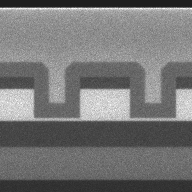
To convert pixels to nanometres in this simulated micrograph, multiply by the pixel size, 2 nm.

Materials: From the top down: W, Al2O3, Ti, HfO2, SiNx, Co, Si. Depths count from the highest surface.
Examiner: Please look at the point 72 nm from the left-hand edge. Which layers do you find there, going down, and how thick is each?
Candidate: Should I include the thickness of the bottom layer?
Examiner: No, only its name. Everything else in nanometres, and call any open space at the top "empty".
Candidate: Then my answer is W 108, Al2O3 112, HfO2 6, SiNx 52, Co 66, Si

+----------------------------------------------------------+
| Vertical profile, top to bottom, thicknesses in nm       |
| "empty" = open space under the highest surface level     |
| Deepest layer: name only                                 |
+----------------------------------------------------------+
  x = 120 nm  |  W 190, Al2O3 30, HfO2 6, SiNx 52, Co 66, Si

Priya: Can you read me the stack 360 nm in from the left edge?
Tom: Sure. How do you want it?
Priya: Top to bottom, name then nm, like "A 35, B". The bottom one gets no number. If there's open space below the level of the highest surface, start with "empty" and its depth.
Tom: W 108, Al2O3 30, Ti 24, HfO2 64, SiNx 52, Co 66, Si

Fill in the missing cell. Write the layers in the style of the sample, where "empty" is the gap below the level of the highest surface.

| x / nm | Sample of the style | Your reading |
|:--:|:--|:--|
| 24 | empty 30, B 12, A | W 108, Al2O3 30, Ti 24, HfO2 64, SiNx 52, Co 66, Si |